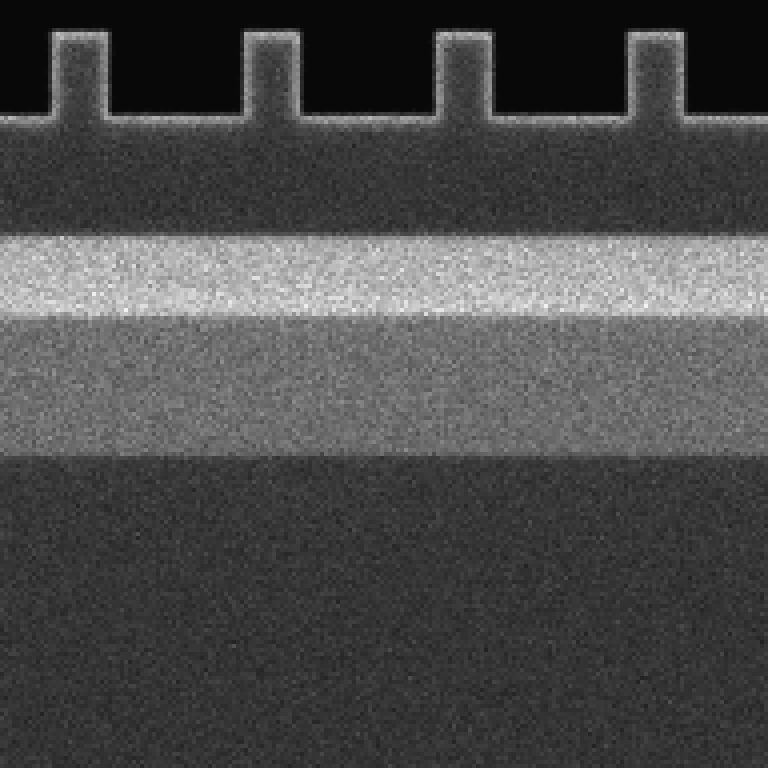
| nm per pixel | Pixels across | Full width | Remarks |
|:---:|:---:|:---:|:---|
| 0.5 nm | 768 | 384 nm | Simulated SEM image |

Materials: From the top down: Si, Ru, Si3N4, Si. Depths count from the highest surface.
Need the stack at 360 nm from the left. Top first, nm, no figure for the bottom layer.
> empty 42, Si 60, Ru 40, Si3N4 70, Si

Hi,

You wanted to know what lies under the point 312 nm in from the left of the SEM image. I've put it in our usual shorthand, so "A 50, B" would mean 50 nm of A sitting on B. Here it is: empty 42, Si 60, Ru 40, Si3N4 70, Si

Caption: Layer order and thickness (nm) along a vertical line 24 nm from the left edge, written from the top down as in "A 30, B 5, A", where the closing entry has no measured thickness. empty 42, Si 60, Ru 40, Si3N4 70, Si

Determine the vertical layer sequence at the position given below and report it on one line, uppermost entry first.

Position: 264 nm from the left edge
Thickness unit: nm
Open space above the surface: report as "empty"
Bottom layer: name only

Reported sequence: empty 42, Si 60, Ru 40, Si3N4 70, Si